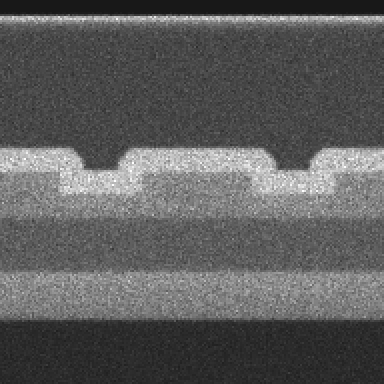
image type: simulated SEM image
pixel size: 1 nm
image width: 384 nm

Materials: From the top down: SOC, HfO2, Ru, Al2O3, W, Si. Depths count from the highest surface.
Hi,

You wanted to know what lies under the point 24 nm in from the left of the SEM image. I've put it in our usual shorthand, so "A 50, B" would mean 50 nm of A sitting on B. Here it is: SOC 132, HfO2 24, Ru 46, Al2O3 54, W 48, Si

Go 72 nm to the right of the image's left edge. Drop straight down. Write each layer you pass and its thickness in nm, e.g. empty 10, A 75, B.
SOC 134, HfO2 44, Ru 24, Al2O3 54, W 48, Si